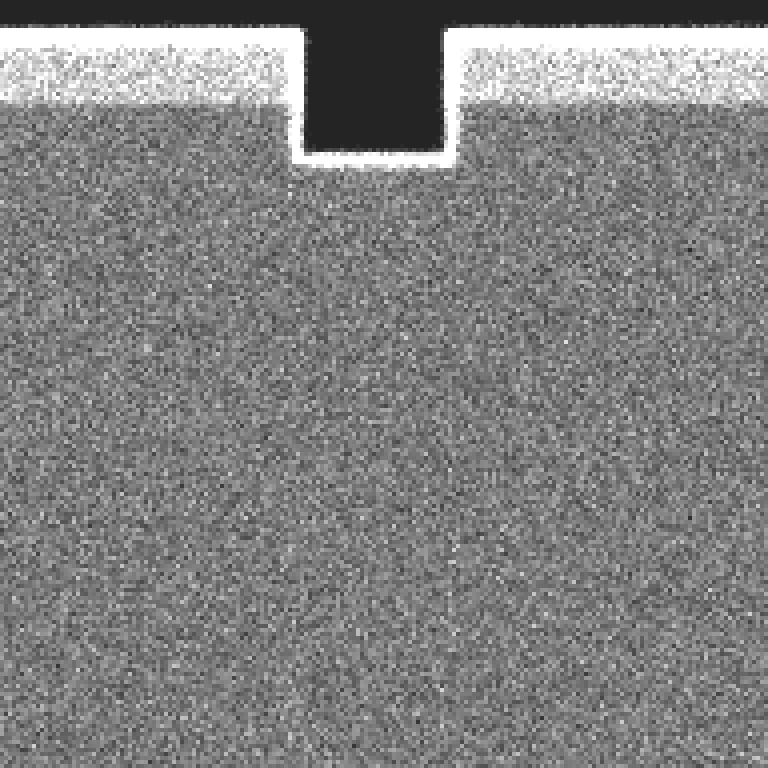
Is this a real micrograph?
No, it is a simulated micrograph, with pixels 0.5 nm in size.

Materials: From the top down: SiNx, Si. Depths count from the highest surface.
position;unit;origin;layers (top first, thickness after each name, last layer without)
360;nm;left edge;SiNx 36, Si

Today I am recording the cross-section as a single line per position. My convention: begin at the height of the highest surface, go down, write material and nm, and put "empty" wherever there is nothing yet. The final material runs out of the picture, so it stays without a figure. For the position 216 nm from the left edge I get empty 62, Si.